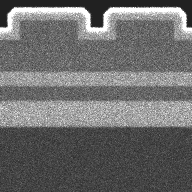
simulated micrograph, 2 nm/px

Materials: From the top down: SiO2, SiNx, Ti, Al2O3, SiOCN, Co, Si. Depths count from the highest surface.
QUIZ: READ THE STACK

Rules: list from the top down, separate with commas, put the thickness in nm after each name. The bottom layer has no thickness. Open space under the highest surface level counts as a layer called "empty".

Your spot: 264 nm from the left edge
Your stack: SiO2 24, SiNx 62, Ti 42, Al2O3 28, SiOCN 30, Co 52, Si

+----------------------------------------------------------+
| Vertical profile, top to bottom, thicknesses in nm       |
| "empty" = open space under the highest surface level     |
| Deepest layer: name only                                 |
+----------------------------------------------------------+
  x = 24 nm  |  empty 4, SiO2 60, SiNx 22, Ti 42, Al2O3 28, SiOCN 30, Co 52, Si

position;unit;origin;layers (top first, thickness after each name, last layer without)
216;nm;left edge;empty 4, SiO2 60, SiNx 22, Ti 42, Al2O3 28, SiOCN 30, Co 52, Si